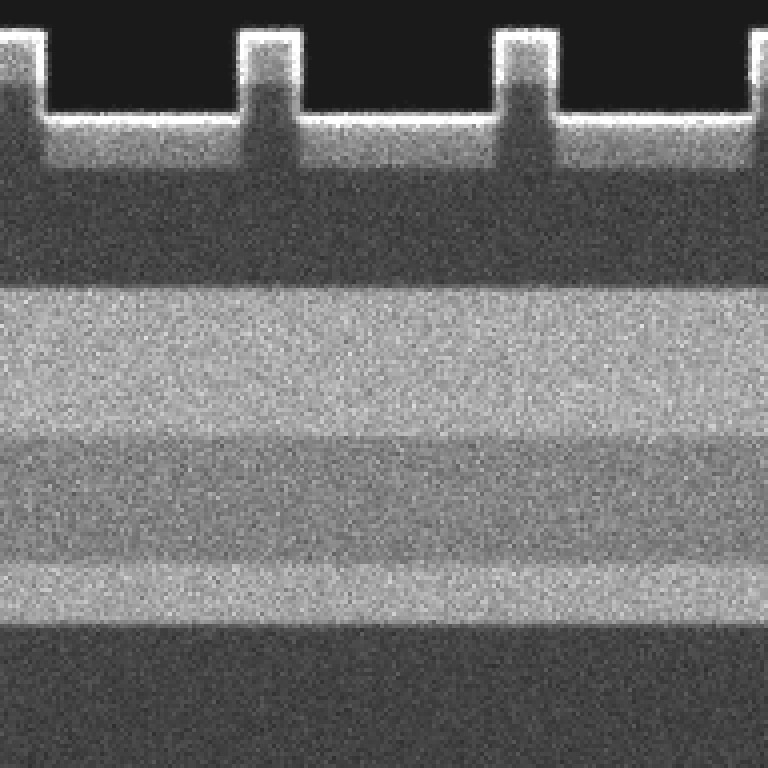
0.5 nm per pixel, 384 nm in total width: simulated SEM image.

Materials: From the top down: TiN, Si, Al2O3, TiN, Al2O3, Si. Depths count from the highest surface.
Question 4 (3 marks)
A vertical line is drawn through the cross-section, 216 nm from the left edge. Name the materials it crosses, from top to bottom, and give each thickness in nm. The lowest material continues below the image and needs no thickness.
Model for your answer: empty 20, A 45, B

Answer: empty 42, TiN 26, Si 60, Al2O3 74, TiN 64, Al2O3 30, Si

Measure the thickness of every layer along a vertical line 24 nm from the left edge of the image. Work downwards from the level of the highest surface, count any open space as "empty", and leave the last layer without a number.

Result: empty 42, TiN 26, Si 60, Al2O3 74, TiN 64, Al2O3 30, Si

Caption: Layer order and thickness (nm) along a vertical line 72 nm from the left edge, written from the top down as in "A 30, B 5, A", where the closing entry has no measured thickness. empty 42, TiN 26, Si 60, Al2O3 74, TiN 64, Al2O3 30, Si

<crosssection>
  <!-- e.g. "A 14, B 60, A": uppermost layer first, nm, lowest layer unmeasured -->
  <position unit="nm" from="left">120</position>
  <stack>TiN 26, Si 102, Al2O3 74, TiN 64, Al2O3 30, Si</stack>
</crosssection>